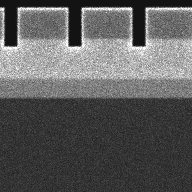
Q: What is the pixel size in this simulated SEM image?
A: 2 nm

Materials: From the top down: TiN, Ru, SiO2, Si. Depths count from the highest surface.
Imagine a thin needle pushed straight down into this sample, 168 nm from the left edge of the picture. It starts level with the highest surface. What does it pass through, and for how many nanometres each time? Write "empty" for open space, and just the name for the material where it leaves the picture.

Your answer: TiN 62, Ru 80, SiO2 38, Si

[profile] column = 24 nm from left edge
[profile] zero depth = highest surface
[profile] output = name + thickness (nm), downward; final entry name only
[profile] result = empty 78, Ru 64, SiO2 38, Si